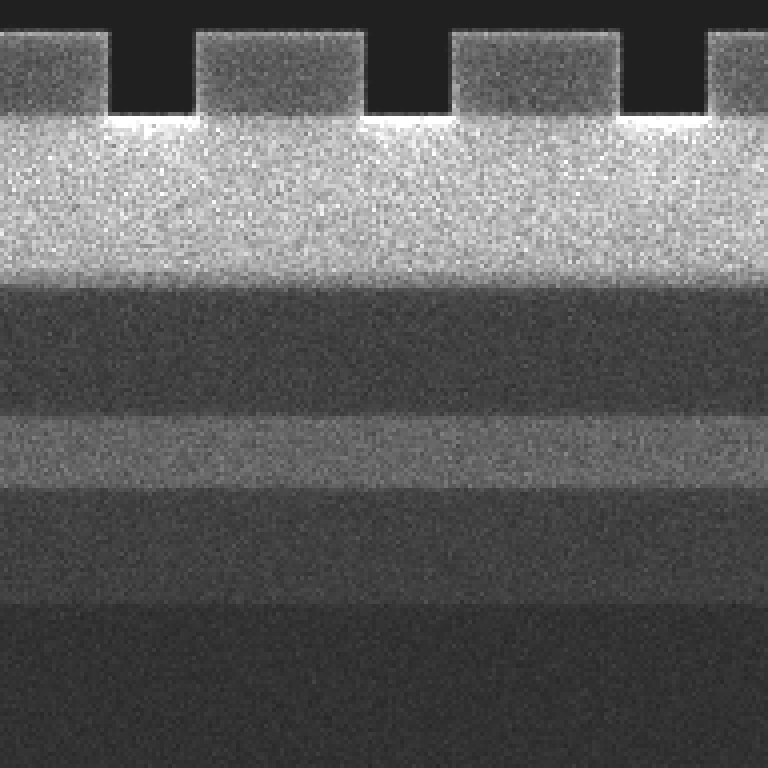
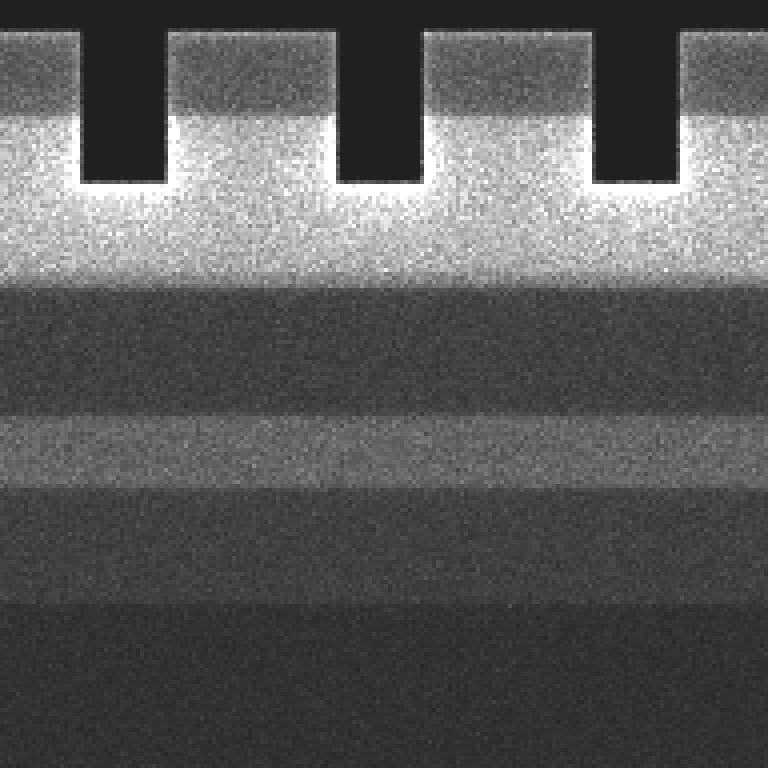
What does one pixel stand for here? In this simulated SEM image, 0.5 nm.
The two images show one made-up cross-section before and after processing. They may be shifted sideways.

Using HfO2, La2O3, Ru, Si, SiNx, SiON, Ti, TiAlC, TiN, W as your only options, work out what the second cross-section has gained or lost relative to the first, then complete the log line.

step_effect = removed HfO2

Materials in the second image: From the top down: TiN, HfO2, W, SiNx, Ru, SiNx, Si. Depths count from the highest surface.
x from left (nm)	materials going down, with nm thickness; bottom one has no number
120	TiN 42, HfO2 78, W 8, SiNx 64, Ru 36, SiNx 58, Si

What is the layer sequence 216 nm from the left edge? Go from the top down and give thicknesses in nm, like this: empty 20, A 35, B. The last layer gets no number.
TiN 42, HfO2 78, W 8, SiNx 64, Ru 36, SiNx 58, Si